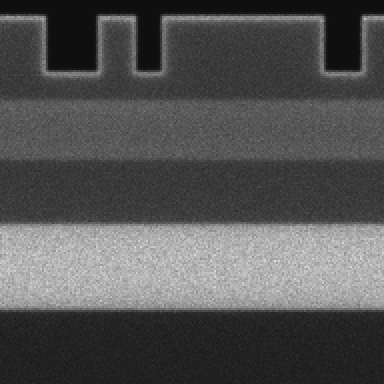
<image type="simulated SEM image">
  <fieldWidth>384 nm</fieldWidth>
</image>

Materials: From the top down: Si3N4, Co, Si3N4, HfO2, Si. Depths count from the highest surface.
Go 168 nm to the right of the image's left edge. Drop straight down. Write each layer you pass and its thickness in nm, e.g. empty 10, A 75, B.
Si3N4 84, Co 60, Si3N4 64, HfO2 86, Si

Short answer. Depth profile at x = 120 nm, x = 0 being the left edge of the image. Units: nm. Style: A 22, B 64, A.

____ Si3N4 84, Co 60, Si3N4 64, HfO2 86, Si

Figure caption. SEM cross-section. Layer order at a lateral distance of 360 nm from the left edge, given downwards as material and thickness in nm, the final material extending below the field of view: empty 56, Si3N4 28, Co 60, Si3N4 64, HfO2 86, Si